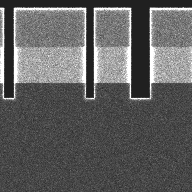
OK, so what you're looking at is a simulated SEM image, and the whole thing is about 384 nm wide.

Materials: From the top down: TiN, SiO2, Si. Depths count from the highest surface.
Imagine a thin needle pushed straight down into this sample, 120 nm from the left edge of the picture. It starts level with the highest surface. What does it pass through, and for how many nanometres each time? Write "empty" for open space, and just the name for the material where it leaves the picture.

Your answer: TiN 78, SiO2 72, Si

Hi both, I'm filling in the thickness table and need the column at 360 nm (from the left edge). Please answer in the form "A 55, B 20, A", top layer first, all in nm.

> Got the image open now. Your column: TiN 78, SiO2 72, Si